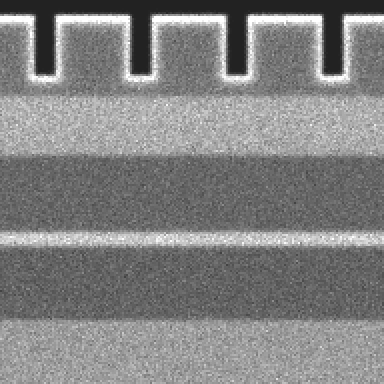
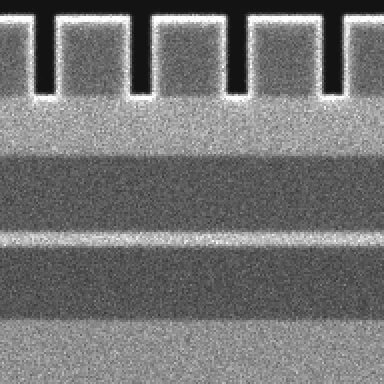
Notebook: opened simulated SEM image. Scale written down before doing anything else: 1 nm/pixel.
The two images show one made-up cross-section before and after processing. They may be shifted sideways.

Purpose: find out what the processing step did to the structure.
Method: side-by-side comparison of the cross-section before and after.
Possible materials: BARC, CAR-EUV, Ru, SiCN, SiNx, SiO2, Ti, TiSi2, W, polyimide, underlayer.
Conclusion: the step removed underlayer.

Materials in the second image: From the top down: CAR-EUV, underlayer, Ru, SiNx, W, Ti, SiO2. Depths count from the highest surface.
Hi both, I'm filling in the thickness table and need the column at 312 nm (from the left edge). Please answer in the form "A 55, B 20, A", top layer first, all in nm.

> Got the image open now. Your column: CAR-EUV 60, underlayer 20, Ru 60, SiNx 76, W 14, Ti 74, SiO2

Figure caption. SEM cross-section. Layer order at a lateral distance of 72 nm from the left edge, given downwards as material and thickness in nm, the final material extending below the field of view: CAR-EUV 60, underlayer 20, Ru 60, SiNx 76, W 14, Ti 74, SiO2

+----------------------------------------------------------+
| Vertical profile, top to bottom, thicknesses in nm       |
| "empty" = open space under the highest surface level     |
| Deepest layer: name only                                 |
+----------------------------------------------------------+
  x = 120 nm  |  CAR-EUV 60, underlayer 20, Ru 60, SiNx 76, W 14, Ti 74, SiO2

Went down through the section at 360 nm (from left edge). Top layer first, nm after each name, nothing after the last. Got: CAR-EUV 60, underlayer 20, Ru 60, SiNx 76, W 14, Ti 74, SiO2